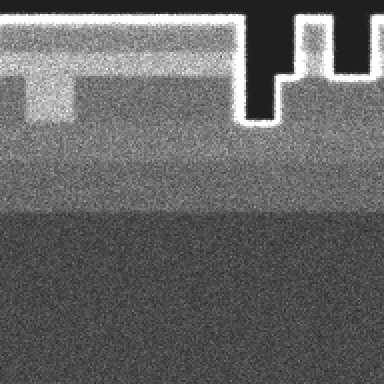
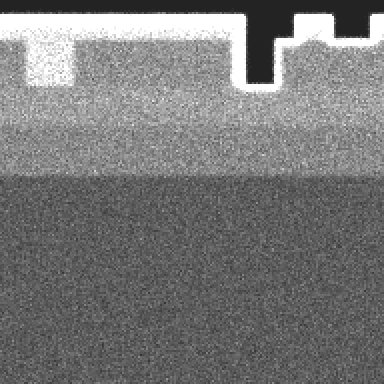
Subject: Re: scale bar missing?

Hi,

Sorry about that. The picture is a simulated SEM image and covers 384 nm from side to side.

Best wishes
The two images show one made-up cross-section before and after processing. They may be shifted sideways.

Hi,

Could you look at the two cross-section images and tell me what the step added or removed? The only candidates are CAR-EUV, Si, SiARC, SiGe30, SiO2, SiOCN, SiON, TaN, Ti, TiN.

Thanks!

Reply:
removed SiARC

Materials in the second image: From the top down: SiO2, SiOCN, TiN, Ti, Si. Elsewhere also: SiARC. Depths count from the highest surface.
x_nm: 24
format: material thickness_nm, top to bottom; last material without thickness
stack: SiO2 24, SiOCN 46, TiN 40, Ti 50, Si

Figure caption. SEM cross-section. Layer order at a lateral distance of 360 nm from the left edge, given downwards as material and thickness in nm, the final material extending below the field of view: empty 24, SiOCN 46, TiN 40, Ti 50, Si